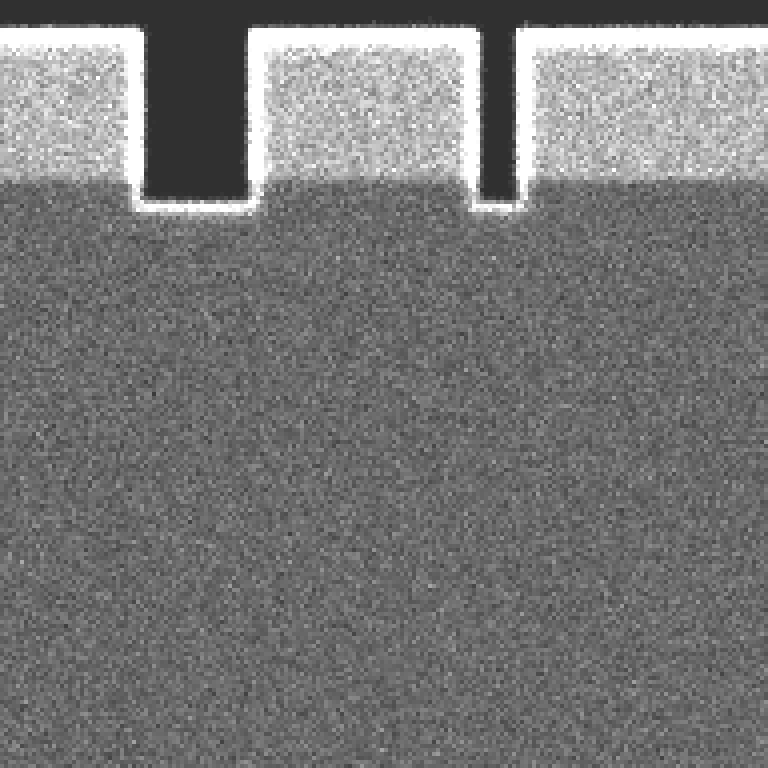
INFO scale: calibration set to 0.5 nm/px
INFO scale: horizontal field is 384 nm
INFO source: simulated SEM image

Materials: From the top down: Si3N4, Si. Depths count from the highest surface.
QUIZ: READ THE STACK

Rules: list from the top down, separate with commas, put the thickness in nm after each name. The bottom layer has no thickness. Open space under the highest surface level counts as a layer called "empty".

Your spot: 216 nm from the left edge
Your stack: Si3N4 74, Si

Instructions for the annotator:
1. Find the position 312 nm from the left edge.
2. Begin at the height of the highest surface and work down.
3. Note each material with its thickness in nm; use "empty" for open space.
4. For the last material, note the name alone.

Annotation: Si3N4 74, Si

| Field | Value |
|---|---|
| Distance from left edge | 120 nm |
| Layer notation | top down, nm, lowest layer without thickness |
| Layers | empty 86, Si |